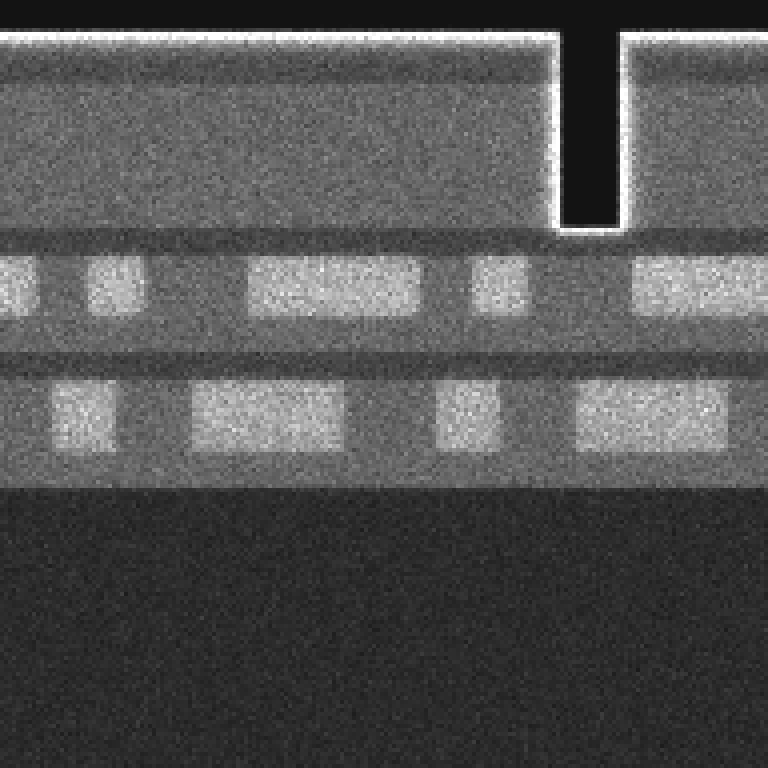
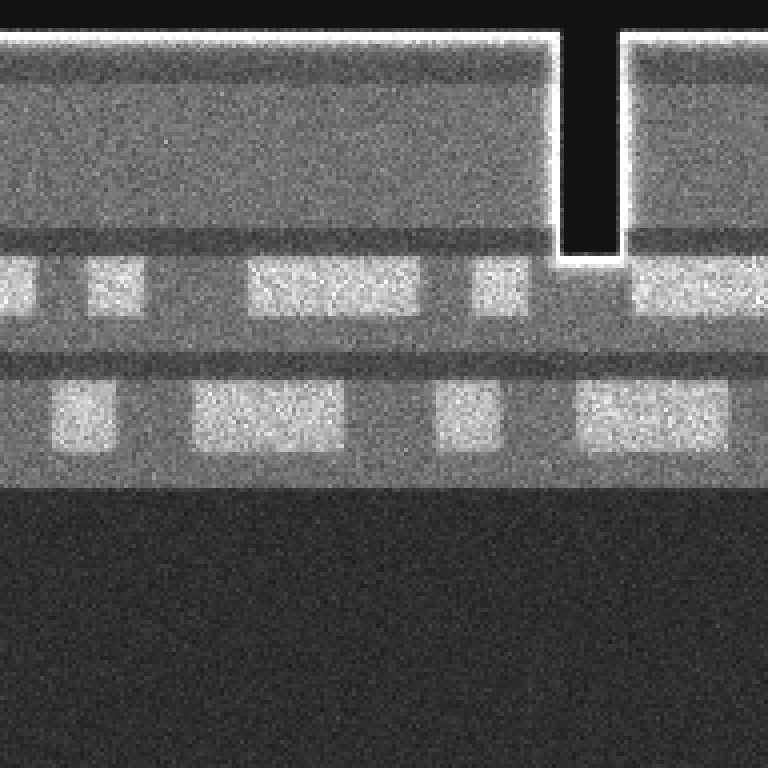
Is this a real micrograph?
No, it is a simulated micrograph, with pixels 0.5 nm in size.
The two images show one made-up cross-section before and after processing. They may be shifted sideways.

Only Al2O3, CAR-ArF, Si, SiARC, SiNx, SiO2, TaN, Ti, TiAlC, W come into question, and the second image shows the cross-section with SiNx removed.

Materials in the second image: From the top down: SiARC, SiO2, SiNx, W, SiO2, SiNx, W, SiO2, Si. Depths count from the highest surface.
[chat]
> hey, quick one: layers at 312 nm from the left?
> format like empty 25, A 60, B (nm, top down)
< SiARC 26, SiO2 72, SiNx 14, SiO2 48, SiNx 14, W 36, SiO2 18, Si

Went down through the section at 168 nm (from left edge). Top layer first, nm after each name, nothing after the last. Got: SiARC 26, SiO2 72, SiNx 14, W 30, SiO2 18, SiNx 14, W 36, SiO2 18, Si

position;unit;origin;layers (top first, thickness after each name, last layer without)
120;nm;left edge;SiARC 26, SiO2 72, SiNx 14, SiO2 48, SiNx 14, W 36, SiO2 18, Si